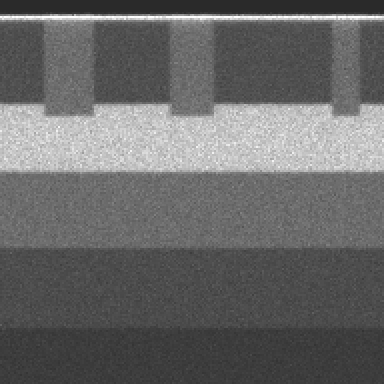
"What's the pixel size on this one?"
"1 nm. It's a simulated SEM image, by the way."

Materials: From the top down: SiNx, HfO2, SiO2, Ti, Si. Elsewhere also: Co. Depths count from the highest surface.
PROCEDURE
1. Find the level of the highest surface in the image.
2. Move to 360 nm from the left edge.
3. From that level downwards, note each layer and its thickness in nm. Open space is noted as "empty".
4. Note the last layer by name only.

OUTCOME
SiNx 88, HfO2 68, SiO2 76, Ti 80, Si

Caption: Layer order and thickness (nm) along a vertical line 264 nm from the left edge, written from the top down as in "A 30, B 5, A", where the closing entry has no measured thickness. SiNx 88, HfO2 68, SiO2 76, Ti 80, Si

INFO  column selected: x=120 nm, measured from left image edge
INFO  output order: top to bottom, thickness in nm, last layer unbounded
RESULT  SiNx 88, HfO2 68, SiO2 76, Ti 80, Si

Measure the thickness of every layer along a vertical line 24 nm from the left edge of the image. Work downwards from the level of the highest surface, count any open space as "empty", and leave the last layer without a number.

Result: SiNx 88, HfO2 68, SiO2 76, Ti 80, Si